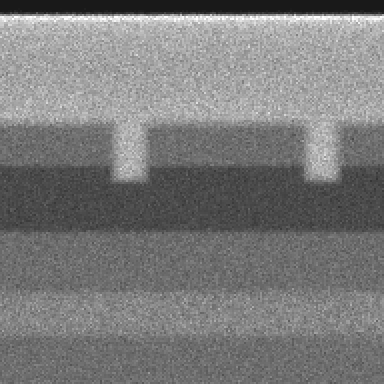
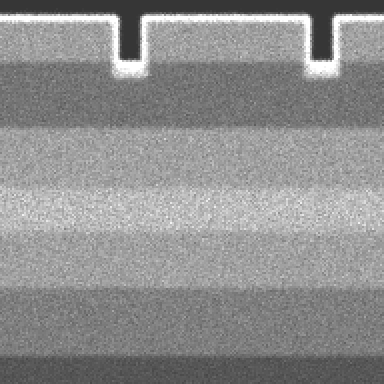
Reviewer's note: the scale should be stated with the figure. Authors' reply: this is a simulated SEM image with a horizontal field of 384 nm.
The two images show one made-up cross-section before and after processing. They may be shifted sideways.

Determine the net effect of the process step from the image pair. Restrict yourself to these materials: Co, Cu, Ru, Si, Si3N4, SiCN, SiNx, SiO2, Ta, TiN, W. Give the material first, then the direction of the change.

W: removed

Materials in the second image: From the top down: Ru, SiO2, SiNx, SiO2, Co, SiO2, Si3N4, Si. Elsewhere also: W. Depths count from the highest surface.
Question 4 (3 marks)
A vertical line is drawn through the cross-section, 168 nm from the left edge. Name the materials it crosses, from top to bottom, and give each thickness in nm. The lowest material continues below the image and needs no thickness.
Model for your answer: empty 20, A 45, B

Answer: Ru 6, SiO2 40, SiNx 66, SiO2 60, Co 44, SiO2 56, Si3N4 68, Si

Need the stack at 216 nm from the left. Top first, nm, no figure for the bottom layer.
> Ru 6, SiO2 40, SiNx 66, SiO2 60, Co 44, SiO2 56, Si3N4 68, Si